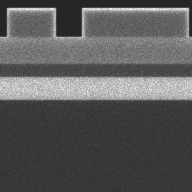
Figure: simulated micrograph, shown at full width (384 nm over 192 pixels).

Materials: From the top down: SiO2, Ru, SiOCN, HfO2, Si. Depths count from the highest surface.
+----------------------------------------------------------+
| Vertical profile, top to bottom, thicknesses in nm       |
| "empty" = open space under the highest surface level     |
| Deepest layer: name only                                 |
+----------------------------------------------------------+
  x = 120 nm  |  empty 58, Ru 54, SiOCN 26, HfO2 46, Si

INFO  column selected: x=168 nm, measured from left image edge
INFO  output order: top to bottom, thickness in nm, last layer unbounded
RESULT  SiO2 58, Ru 54, SiOCN 26, HfO2 46, Si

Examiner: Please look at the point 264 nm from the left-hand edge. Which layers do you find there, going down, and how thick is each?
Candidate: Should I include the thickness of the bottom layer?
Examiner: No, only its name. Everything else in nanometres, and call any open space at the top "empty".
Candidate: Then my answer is SiO2 58, Ru 54, SiOCN 26, HfO2 46, Si